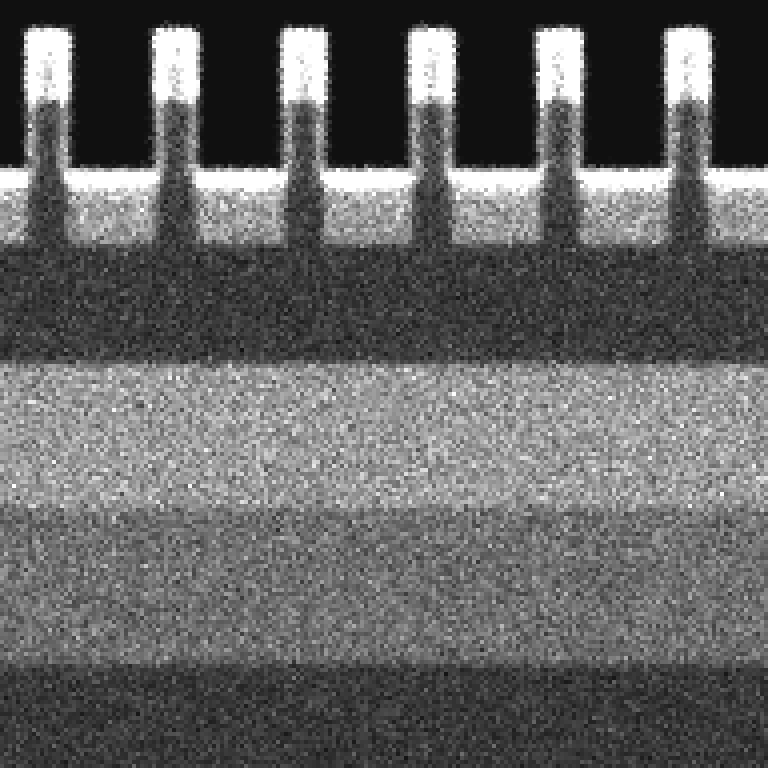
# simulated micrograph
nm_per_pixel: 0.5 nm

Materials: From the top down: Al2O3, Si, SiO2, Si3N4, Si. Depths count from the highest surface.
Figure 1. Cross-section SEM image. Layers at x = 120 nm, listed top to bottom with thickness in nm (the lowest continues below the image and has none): empty 70, SiO2 36, Si 60, SiO2 72, Si3N4 78, Si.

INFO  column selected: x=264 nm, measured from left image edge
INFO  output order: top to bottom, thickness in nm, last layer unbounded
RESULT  empty 70, SiO2 36, Si 60, SiO2 72, Si3N4 78, Si